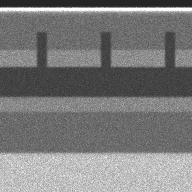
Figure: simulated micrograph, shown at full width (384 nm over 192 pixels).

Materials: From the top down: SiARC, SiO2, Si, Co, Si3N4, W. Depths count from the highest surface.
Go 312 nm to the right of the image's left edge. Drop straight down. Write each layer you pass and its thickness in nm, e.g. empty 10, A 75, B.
SiARC 84, SiO2 34, Si 60, Co 30, Si3N4 82, W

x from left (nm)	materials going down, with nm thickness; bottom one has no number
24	SiARC 84, SiO2 34, Si 60, Co 30, Si3N4 82, W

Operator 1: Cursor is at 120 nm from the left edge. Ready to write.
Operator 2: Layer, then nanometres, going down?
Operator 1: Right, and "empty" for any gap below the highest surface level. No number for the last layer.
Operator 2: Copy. SiARC 84, SiO2 34, Si 60, Co 30, Si3N4 82, W